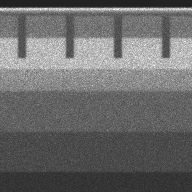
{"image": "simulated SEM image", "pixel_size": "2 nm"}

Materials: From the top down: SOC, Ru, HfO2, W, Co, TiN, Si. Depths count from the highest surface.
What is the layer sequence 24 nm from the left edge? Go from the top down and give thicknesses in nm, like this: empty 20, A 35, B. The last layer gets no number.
SOC 16, Ru 44, HfO2 62, W 44, Co 82, TiN 80, Si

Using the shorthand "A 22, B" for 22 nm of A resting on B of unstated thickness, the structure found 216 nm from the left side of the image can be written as SOC 16, Ru 44, HfO2 62, W 44, Co 82, TiN 80, Si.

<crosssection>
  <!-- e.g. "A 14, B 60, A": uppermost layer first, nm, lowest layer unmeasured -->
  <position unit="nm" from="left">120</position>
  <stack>SOC 16, Ru 44, HfO2 62, W 44, Co 82, TiN 80, Si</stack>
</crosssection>